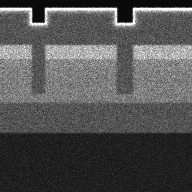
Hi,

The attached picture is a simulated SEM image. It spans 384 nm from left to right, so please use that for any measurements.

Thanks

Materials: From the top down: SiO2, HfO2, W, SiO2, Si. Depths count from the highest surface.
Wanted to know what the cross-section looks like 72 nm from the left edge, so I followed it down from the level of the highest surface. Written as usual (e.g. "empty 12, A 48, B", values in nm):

empty 30, SiO2 142, W 18, SiO2 60, Si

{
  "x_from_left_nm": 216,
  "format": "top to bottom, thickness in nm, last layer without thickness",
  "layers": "SiO2 74, HfO2 28, W 88, SiO2 60, Si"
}